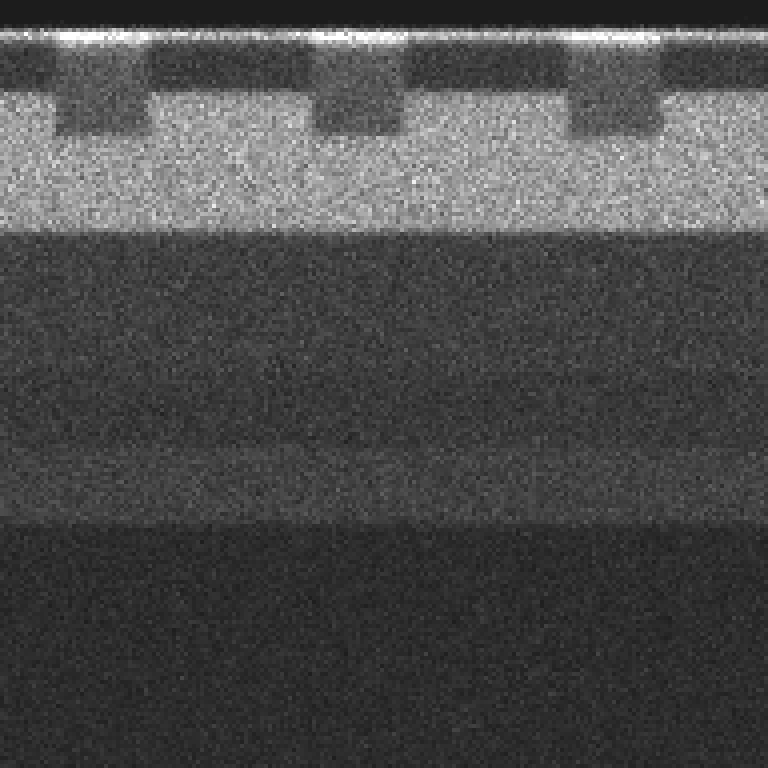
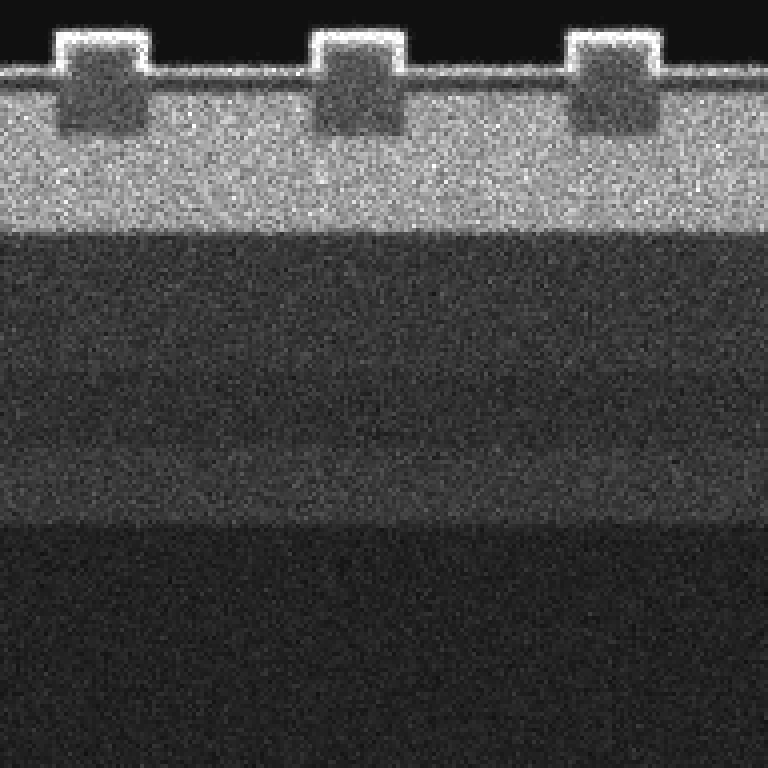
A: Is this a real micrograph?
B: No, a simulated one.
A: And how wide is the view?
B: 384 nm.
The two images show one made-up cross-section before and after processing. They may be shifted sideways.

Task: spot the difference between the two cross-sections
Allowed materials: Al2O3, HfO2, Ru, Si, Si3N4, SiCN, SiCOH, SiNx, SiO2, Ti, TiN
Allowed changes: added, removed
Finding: removed SiNx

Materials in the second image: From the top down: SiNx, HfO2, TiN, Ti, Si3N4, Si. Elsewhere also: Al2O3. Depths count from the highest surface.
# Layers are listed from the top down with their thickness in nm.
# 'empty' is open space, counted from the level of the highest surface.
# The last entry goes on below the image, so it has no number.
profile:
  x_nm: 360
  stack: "empty 18, SiNx 12, HfO2 70, TiN 70, Ti 38, Si3N4 38, Si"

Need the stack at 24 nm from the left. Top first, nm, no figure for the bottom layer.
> empty 18, SiNx 12, HfO2 70, TiN 70, Ti 38, Si3N4 38, Si